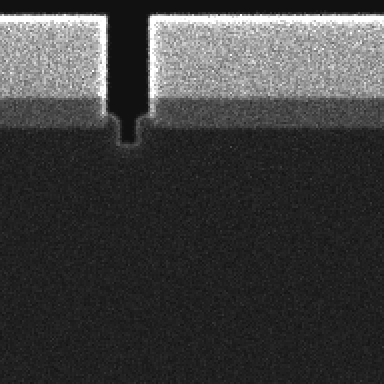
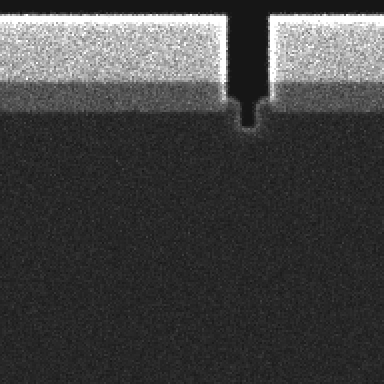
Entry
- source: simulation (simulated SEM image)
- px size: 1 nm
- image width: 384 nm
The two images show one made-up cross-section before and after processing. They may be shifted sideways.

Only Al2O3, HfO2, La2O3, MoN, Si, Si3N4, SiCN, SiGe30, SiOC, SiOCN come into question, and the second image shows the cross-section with HfO2 removed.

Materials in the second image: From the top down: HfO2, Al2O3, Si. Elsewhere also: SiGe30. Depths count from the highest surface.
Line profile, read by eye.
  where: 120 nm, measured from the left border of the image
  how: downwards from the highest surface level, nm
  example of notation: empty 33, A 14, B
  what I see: HfO2 66, Al2O3 30, Si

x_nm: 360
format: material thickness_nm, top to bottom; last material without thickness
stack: HfO2 66, Al2O3 30, Si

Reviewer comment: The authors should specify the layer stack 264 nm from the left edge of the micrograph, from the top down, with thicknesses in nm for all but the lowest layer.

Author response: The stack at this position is empty 82, SiGe30 44, Si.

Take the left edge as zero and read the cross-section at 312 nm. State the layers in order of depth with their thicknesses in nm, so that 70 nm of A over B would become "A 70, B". HfO2 66, Al2O3 30, Si